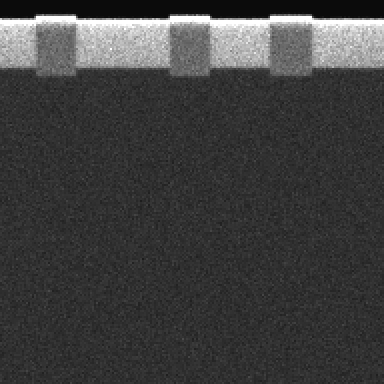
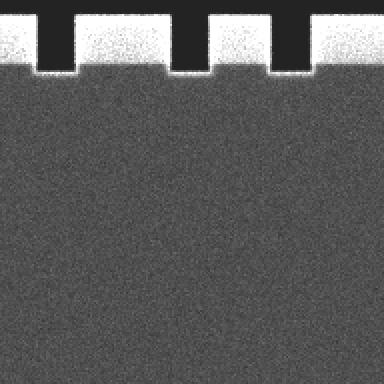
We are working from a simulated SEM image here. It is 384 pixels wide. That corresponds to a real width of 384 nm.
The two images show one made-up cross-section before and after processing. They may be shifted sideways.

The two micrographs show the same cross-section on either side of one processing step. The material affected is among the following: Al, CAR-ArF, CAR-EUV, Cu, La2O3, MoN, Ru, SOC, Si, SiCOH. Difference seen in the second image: SOC removed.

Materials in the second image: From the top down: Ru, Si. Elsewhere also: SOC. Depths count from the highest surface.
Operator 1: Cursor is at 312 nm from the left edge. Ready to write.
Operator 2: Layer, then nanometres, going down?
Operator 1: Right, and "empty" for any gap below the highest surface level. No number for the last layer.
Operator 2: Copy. Ru 48, Si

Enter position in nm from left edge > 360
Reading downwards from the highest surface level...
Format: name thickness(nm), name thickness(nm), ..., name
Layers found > Ru 48, Si